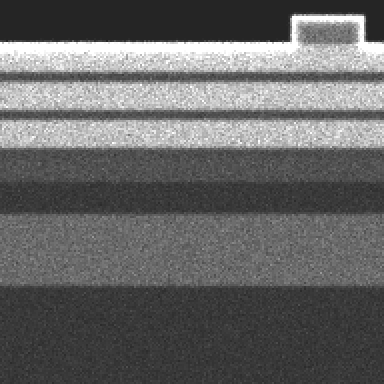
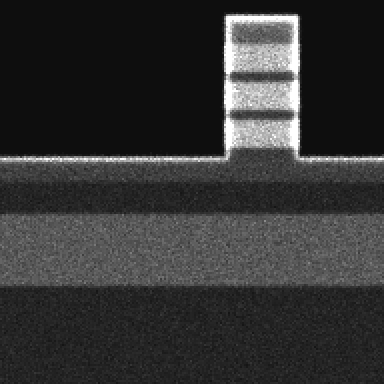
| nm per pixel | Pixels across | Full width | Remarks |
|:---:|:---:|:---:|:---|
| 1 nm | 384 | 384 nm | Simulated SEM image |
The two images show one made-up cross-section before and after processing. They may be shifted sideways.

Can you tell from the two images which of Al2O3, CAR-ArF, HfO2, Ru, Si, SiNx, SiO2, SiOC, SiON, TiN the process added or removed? Yes, it removed HfO2 and SiNx.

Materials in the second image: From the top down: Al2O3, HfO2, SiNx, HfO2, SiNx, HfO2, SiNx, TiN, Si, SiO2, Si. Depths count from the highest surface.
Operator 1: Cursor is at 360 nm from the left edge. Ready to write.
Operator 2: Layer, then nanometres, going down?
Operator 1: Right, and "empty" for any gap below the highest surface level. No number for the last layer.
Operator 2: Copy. empty 142, TiN 24, Si 32, SiO2 72, Si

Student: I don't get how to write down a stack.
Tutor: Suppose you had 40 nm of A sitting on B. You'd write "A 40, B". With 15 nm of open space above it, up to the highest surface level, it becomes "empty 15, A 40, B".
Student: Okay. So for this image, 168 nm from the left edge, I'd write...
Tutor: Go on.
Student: empty 142, TiN 24, Si 32, SiO2 72, Si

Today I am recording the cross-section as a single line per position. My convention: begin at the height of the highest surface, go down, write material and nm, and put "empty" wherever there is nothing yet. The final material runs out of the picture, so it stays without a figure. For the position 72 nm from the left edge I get empty 142, TiN 24, Si 32, SiO2 72, Si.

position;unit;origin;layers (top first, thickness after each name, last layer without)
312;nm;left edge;empty 142, TiN 24, Si 32, SiO2 72, Si